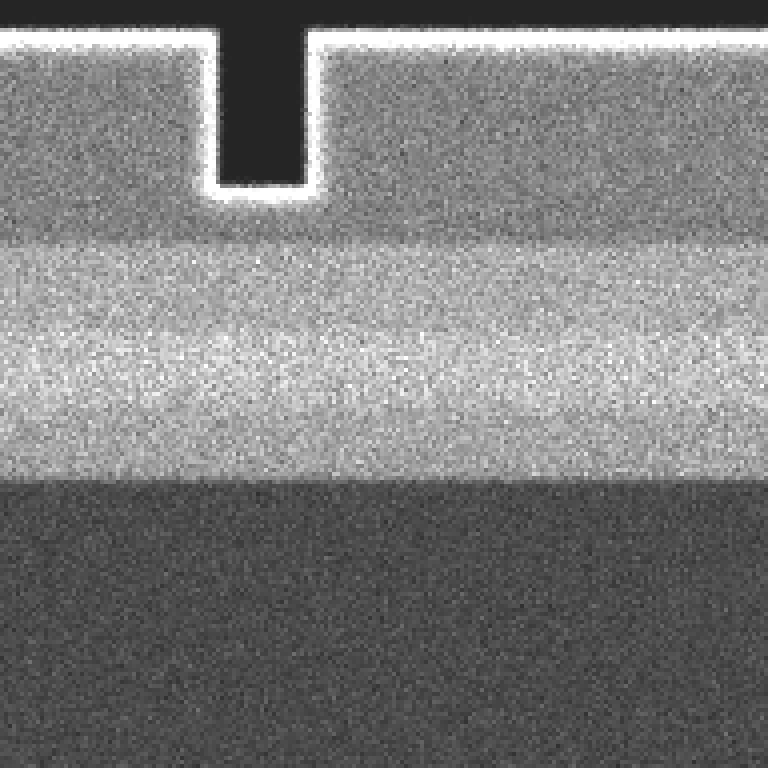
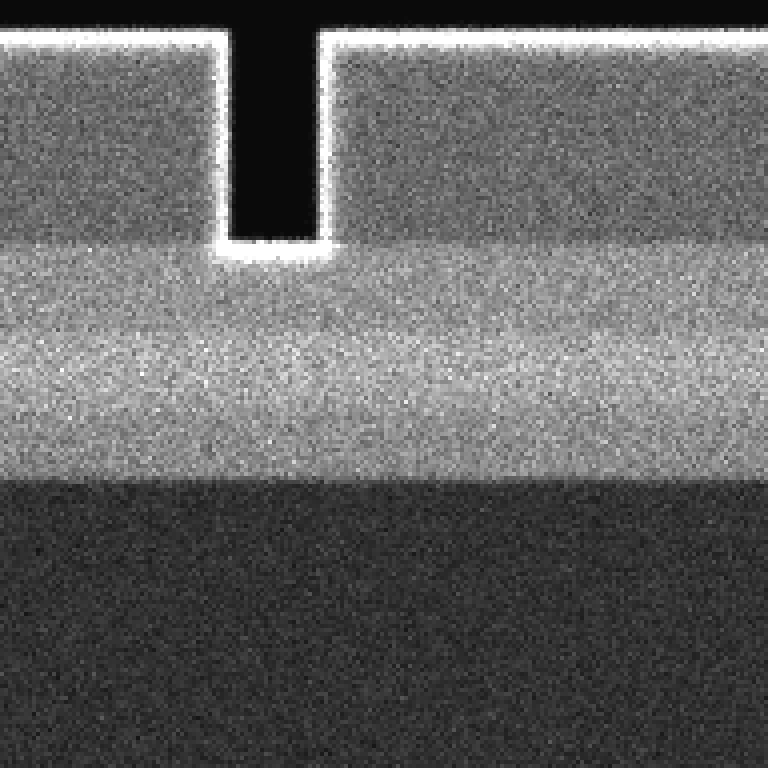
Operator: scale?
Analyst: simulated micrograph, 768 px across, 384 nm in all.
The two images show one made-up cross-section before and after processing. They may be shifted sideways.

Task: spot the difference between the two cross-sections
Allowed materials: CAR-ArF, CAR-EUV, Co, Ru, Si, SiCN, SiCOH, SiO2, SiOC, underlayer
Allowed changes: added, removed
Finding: removed underlayer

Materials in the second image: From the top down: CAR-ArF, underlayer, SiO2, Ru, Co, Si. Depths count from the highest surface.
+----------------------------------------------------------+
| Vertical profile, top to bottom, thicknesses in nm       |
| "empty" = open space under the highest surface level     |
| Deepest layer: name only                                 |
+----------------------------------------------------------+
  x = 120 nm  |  empty 106, SiO2 44, Ru 38, Co 36, Si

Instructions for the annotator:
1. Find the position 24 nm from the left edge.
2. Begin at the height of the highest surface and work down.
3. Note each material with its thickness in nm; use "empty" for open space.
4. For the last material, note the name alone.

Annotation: CAR-ArF 78, underlayer 28, SiO2 44, Ru 38, Co 36, Si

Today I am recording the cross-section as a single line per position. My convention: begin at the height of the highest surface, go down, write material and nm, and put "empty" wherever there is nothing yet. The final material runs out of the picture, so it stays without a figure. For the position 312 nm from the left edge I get CAR-ArF 78, underlayer 28, SiO2 44, Ru 38, Co 36, Si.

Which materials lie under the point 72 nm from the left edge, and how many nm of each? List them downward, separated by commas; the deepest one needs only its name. CAR-ArF 78, underlayer 28, SiO2 44, Ru 38, Co 36, Si